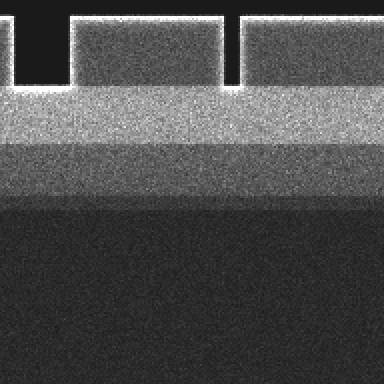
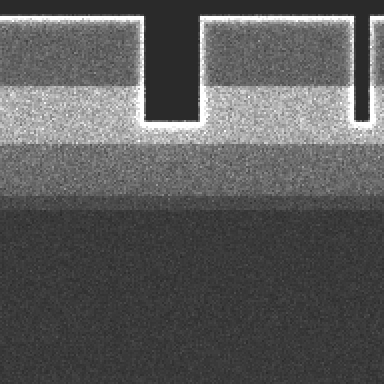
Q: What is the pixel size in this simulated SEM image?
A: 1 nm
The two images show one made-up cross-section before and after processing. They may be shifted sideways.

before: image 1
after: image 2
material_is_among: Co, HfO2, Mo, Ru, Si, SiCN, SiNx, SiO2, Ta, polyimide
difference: HfO2, removed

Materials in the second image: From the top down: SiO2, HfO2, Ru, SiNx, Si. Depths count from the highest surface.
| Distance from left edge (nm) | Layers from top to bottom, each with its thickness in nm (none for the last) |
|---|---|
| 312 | SiO2 70, HfO2 58, Ru 52, SiNx 14, Si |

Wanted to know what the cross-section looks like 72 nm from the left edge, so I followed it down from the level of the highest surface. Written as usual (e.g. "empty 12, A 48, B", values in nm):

SiO2 70, HfO2 58, Ru 52, SiNx 14, Si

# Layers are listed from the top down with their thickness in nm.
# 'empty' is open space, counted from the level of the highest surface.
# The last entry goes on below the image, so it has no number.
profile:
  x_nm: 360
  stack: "empty 106, HfO2 22, Ru 52, SiNx 14, Si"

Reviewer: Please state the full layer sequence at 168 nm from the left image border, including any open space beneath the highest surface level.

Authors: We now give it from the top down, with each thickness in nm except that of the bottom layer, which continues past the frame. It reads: empty 106, HfO2 22, Ru 52, SiNx 14, Si